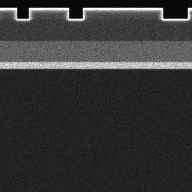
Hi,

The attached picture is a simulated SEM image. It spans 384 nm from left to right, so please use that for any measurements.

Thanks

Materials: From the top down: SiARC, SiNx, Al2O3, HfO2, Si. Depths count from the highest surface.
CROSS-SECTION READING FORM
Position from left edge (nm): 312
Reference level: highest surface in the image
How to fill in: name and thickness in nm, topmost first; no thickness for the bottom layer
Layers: SiARC 22, SiNx 44, Al2O3 42, HfO2 14, Si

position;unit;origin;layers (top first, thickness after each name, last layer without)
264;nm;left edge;SiARC 22, SiNx 44, Al2O3 42, HfO2 14, Si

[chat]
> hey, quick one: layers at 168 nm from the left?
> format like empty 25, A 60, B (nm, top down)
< SiARC 22, SiNx 44, Al2O3 42, HfO2 14, Si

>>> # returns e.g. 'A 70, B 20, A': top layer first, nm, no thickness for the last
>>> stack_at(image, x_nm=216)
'SiARC 22, SiNx 44, Al2O3 42, HfO2 14, Si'